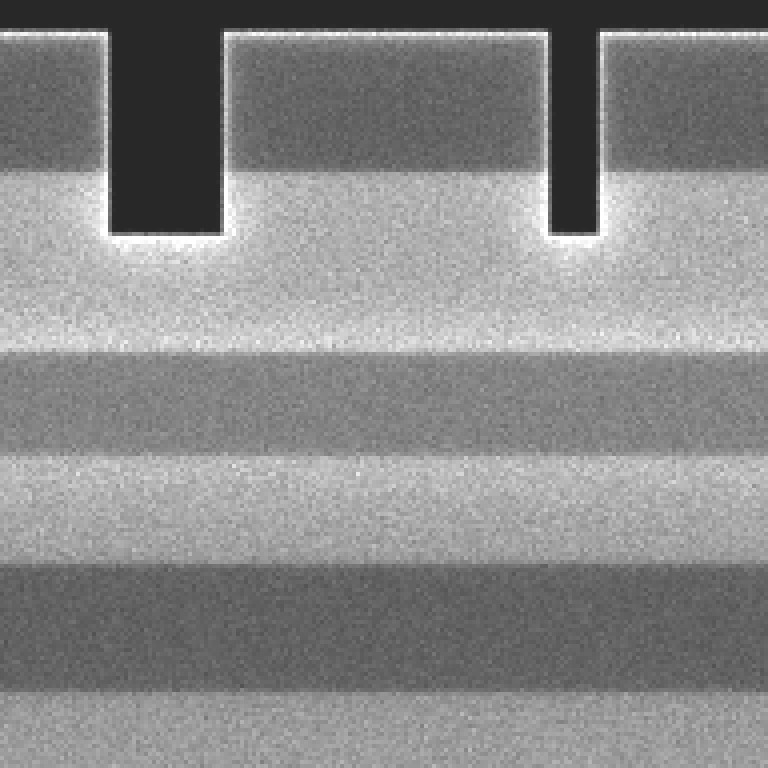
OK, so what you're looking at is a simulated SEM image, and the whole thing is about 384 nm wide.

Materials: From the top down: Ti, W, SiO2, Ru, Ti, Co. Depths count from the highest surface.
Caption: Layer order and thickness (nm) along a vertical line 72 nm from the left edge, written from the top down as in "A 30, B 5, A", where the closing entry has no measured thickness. empty 102, W 58, SiO2 52, Ru 54, Ti 64, Co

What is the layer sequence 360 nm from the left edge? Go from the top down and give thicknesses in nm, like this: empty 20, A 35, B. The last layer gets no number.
Ti 70, W 90, SiO2 52, Ru 54, Ti 64, Co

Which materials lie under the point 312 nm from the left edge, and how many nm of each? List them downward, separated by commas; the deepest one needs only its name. Ti 70, W 90, SiO2 52, Ru 54, Ti 64, Co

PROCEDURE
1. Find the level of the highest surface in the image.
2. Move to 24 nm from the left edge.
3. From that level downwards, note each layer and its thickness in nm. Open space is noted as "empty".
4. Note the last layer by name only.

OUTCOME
Ti 70, W 90, SiO2 52, Ru 54, Ti 64, Co